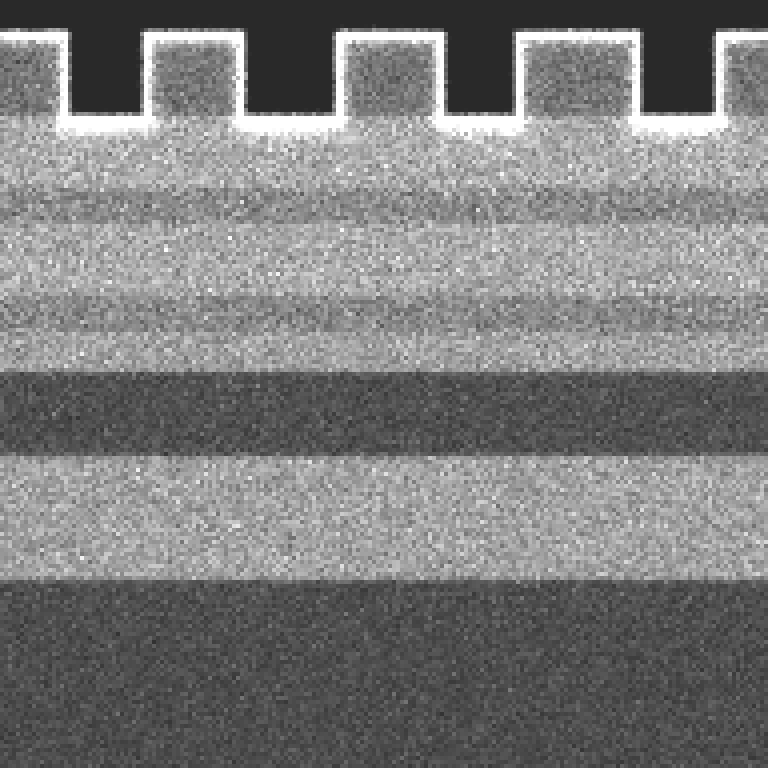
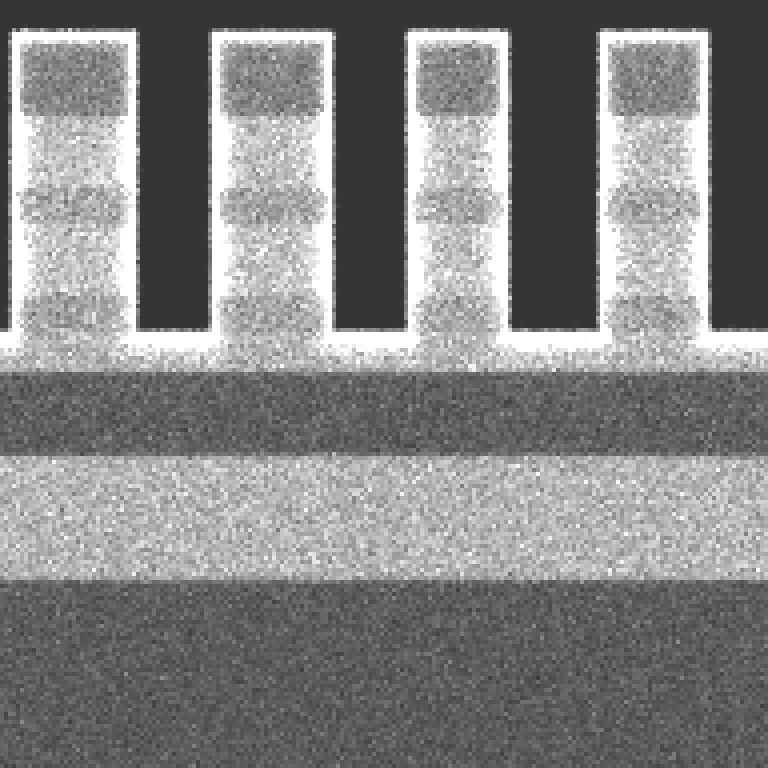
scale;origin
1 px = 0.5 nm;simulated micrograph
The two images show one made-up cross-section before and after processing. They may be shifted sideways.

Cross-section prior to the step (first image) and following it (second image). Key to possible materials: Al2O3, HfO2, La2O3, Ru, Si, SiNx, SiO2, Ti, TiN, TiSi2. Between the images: Al2O3 and TiN was removed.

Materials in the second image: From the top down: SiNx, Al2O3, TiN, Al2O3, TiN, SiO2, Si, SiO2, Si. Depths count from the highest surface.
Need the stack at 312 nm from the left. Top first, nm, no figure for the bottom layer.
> SiNx 42, Al2O3 36, TiN 18, Al2O3 36, TiN 18, SiO2 20, Si 42, SiO2 62, Si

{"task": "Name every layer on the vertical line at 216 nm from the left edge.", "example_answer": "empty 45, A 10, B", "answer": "SiNx 42, Al2O3 36, TiN 18, Al2O3 36, TiN 18, SiO2 20, Si 42, SiO2 62, Si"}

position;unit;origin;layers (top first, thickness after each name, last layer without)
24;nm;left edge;SiNx 42, Al2O3 36, TiN 18, Al2O3 36, TiN 18, SiO2 20, Si 42, SiO2 62, Si